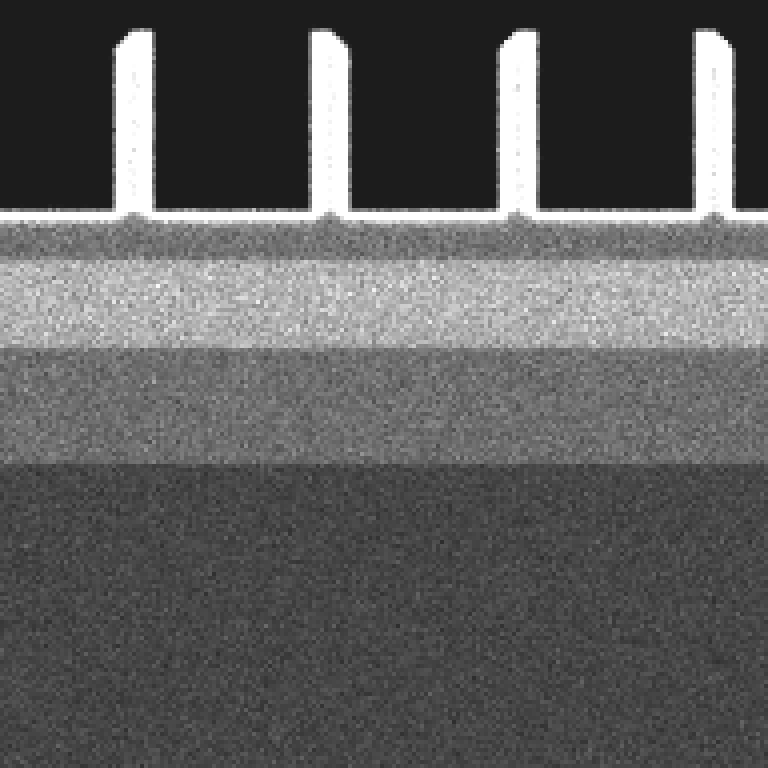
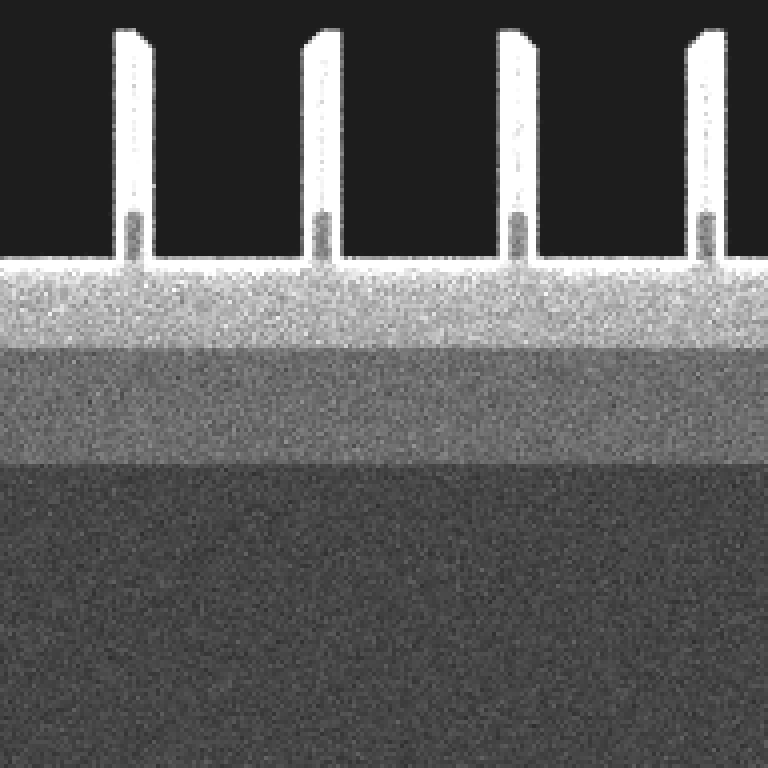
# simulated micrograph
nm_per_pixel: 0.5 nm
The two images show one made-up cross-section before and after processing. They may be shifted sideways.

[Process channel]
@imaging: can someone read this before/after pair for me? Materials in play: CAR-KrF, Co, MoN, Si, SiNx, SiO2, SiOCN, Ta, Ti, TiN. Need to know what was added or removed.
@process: SiNx removed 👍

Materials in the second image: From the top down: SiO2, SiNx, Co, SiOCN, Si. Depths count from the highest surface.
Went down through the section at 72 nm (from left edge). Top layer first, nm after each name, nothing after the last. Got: empty 6, SiO2 84, SiNx 24, Co 44, SiOCN 58, Si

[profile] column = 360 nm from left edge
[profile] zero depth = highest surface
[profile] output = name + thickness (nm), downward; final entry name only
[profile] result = SiO2 90, SiNx 24, Co 44, SiOCN 58, Si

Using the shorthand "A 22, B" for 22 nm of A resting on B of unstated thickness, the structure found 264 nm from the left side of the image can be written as empty 6, SiO2 84, SiNx 24, Co 44, SiOCN 58, Si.